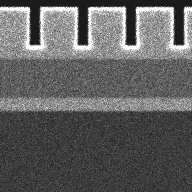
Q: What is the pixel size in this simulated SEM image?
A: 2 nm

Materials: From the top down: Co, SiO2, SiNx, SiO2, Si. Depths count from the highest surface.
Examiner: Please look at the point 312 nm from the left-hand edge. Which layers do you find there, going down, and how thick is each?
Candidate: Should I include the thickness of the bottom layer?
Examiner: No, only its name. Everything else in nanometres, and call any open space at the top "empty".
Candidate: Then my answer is Co 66, SiO2 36, SiNx 78, SiO2 26, Si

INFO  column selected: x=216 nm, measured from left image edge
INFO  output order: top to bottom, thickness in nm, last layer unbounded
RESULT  Co 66, SiO2 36, SiNx 78, SiO2 26, Si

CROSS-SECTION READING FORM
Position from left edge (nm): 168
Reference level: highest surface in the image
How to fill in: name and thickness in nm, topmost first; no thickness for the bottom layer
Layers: empty 76, SiO2 26, SiNx 78, SiO2 26, Si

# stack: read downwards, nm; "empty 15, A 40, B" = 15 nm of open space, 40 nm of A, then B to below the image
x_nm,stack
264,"empty 76, SiO2 26, SiNx 78, SiO2 26, Si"